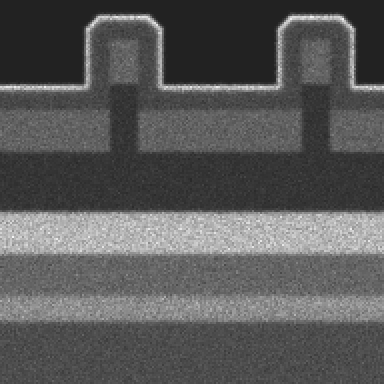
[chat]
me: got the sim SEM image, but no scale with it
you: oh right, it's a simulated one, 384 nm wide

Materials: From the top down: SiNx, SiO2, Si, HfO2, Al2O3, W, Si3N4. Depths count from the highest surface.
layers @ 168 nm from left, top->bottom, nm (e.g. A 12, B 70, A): empty 70, SiNx 24, SiO2 42, Si 60, HfO2 42, Al2O3 42, W 26, Si3N4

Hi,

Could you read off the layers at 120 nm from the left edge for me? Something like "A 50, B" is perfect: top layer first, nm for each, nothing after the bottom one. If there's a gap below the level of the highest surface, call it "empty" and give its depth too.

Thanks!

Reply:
SiNx 24, Al2O3 44, Si 128, HfO2 42, Al2O3 42, W 26, Si3N4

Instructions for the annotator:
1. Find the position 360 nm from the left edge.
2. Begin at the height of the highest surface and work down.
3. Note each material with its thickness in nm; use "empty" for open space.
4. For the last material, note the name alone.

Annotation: empty 70, SiNx 24, SiO2 42, Si 60, HfO2 42, Al2O3 42, W 26, Si3N4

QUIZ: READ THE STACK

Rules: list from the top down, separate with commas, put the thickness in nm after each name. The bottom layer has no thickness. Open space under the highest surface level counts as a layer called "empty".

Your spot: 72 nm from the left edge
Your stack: empty 70, SiNx 24, SiO2 42, Si 60, HfO2 42, Al2O3 42, W 26, Si3N4